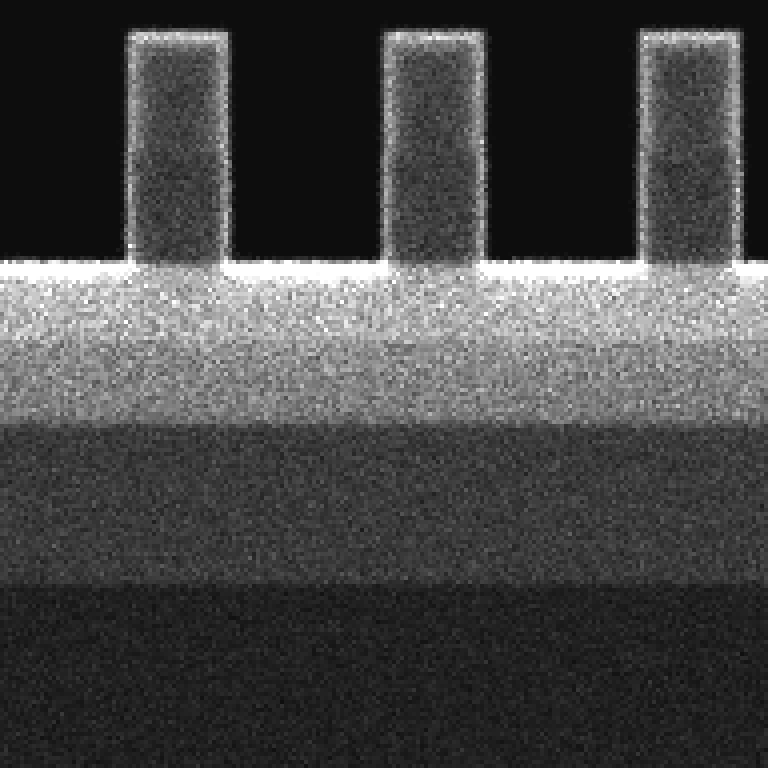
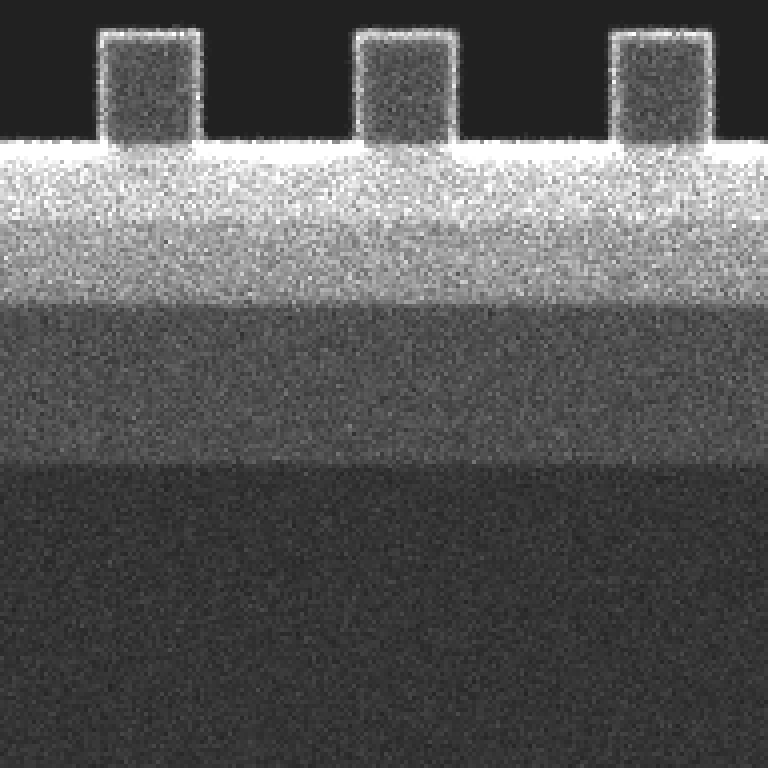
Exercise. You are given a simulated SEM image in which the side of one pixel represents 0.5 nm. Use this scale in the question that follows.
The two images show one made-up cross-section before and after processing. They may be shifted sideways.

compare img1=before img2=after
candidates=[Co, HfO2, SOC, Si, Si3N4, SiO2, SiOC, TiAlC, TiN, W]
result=removed:SOC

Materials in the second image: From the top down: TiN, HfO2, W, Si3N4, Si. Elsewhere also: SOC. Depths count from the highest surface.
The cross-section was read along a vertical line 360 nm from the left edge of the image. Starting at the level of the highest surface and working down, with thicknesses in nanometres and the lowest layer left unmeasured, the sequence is empty 56, HfO2 38, W 42, Si3N4 80, Si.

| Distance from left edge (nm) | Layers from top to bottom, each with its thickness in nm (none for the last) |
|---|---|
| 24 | empty 56, HfO2 38, W 42, Si3N4 80, Si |